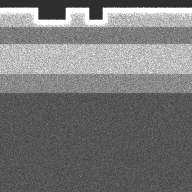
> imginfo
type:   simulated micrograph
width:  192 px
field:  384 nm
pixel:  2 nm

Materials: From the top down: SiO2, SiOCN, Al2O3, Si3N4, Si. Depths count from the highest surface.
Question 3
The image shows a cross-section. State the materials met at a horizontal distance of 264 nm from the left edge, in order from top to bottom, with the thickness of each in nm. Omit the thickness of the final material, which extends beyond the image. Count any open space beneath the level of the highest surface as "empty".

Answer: SiO2 38, SiOCN 34, Al2O3 60, Si3N4 38, Si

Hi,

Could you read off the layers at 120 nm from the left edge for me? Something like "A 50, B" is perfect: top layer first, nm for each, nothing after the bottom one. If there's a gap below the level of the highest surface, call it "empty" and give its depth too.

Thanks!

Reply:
empty 24, SiO2 14, SiOCN 34, Al2O3 60, Si3N4 38, Si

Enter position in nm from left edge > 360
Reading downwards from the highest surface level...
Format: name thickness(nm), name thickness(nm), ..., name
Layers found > SiO2 38, SiOCN 34, Al2O3 60, Si3N4 38, Si